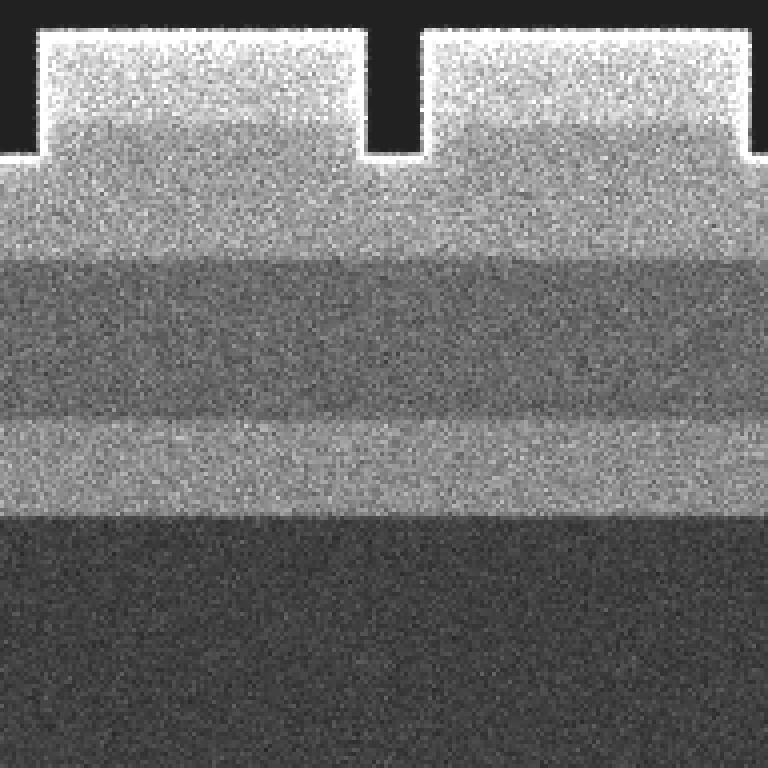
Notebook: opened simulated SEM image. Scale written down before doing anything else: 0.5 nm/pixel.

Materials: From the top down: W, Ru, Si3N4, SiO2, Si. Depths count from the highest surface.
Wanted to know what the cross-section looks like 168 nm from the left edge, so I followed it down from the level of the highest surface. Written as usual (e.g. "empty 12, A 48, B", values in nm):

W 46, Ru 68, Si3N4 80, SiO2 48, Si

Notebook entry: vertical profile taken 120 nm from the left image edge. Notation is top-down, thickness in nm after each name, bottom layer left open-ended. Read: W 46, Ru 68, Si3N4 80, SiO2 48, Si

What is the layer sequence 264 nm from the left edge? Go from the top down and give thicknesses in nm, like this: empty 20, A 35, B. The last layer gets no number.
W 46, Ru 68, Si3N4 80, SiO2 48, Si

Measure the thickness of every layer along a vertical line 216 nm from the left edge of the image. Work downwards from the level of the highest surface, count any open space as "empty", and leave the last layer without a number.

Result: W 46, Ru 68, Si3N4 80, SiO2 48, Si